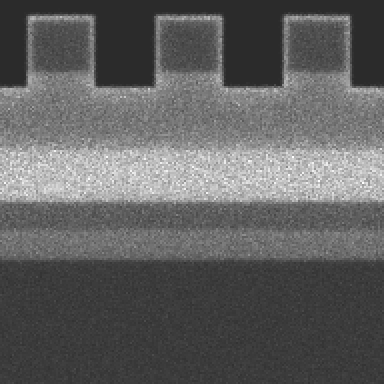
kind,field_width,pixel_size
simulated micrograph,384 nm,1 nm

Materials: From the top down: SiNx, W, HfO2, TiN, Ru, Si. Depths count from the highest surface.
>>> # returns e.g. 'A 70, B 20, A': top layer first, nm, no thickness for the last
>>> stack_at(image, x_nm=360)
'empty 72, W 62, HfO2 52, TiN 28, Ru 30, Si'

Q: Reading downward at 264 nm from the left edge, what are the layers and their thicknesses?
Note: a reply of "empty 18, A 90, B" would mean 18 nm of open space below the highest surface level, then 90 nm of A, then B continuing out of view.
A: empty 72, W 62, HfO2 52, TiN 28, Ru 30, Si